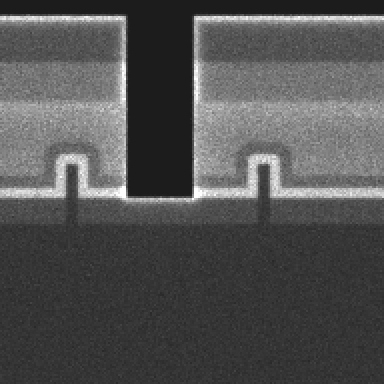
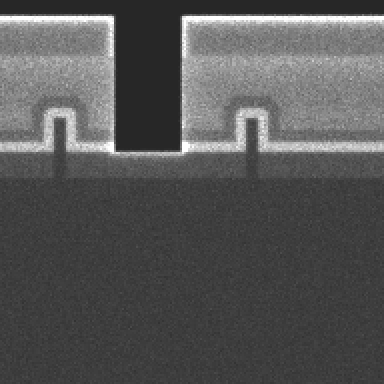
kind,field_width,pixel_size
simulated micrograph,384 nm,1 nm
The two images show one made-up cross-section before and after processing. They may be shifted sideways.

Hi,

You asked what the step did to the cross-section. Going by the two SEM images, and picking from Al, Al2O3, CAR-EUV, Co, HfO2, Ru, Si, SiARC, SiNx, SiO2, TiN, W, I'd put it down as SiARC, removed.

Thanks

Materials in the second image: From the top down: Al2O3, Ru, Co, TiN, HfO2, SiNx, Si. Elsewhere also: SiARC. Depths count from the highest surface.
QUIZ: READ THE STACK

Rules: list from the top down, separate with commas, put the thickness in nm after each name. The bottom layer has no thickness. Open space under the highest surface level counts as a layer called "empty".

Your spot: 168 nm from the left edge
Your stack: empty 136, SiNx 26, Si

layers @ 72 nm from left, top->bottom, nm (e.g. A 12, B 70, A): Al2O3 40, Ru 28, Co 12, TiN 14, HfO2 42, SiNx 26, Si